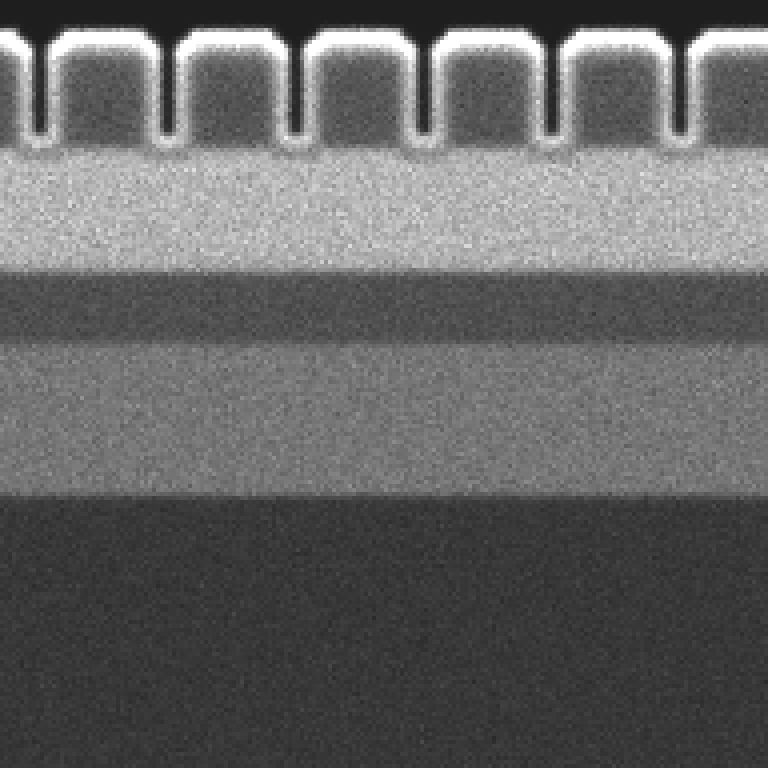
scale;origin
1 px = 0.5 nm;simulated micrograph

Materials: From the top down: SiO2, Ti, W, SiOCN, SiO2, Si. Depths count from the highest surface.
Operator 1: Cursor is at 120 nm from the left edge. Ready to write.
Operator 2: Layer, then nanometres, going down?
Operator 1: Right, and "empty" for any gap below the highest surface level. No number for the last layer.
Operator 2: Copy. SiO2 12, Ti 46, W 62, SiOCN 36, SiO2 76, Si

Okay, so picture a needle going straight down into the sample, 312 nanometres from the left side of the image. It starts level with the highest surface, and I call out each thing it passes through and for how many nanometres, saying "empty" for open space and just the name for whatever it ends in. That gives SiO2 12, Ti 46, W 62, SiOCN 36, SiO2 76, Si